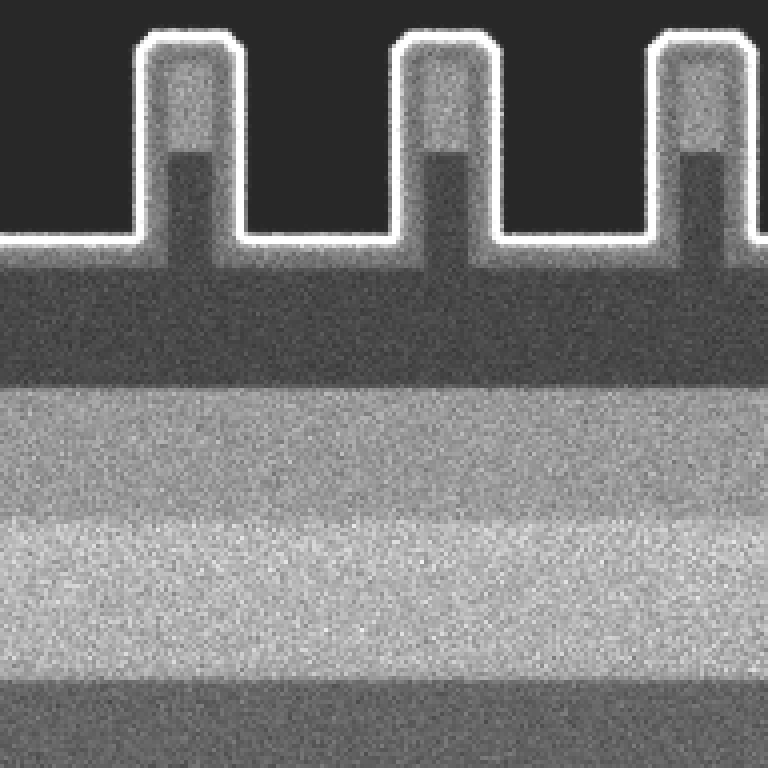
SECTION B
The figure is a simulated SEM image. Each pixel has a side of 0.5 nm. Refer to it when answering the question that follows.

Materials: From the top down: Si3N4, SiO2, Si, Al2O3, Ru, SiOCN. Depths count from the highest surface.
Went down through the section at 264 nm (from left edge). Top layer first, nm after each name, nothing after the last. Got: empty 102, Si3N4 16, Si 60, Al2O3 66, Ru 80, SiOCN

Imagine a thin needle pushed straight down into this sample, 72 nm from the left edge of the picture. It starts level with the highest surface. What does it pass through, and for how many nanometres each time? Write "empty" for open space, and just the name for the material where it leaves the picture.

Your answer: empty 4, Si3N4 114, Si 60, Al2O3 66, Ru 80, SiOCN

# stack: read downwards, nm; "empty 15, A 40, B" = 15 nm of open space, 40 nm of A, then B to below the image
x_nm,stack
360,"Si3N4 16, SiO2 44, Si 118, Al2O3 66, Ru 80, SiOCN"